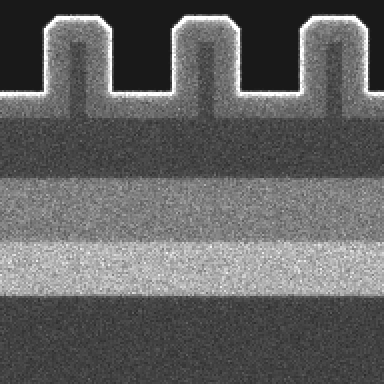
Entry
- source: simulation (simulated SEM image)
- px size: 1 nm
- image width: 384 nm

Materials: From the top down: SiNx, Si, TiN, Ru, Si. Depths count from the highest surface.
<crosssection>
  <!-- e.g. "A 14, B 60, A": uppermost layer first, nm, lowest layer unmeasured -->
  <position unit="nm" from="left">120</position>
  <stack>empty 76, SiNx 26, Si 60, TiN 64, Ru 54, Si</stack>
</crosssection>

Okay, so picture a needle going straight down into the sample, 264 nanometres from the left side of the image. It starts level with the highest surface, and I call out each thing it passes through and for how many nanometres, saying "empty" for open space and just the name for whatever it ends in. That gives empty 76, SiNx 26, Si 60, TiN 64, Ru 54, Si